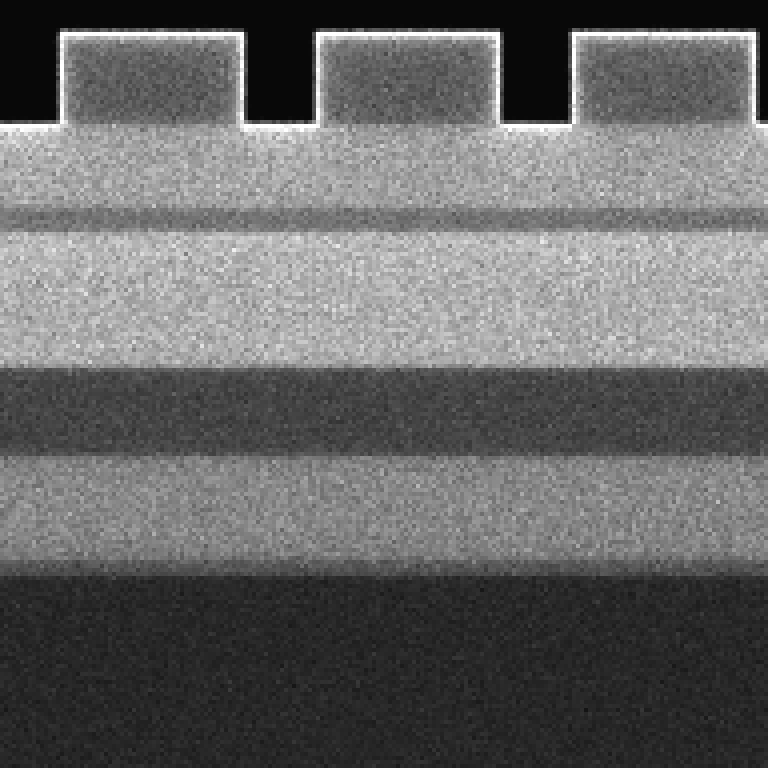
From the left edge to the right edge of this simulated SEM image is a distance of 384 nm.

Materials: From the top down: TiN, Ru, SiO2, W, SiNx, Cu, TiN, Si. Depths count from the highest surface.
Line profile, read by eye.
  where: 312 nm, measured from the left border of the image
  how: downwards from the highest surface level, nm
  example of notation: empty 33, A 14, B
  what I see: TiN 46, Ru 42, SiO2 12, W 68, SiNx 44, Cu 52, TiN 8, Si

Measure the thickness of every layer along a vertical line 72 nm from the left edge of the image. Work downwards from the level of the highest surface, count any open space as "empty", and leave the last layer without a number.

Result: TiN 46, Ru 42, SiO2 12, W 68, SiNx 44, Cu 52, TiN 8, Si